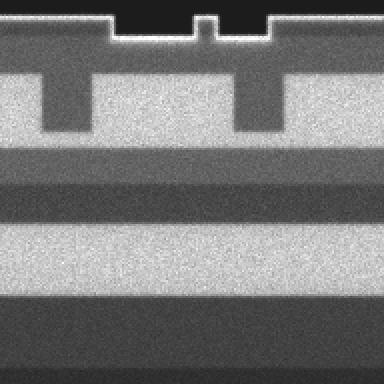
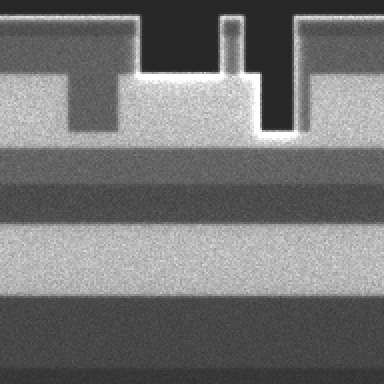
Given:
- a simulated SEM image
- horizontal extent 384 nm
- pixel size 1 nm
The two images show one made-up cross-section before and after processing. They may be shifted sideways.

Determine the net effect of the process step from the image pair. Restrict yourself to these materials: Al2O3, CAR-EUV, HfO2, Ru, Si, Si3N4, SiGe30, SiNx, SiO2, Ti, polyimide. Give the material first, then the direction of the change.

SiO2: removed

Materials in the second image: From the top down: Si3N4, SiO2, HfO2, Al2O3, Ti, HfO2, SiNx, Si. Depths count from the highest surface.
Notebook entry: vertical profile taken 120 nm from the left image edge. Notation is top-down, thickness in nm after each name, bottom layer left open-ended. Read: Si3N4 20, SiO2 38, HfO2 74, Al2O3 36, Ti 40, HfO2 72, SiNx 72, Si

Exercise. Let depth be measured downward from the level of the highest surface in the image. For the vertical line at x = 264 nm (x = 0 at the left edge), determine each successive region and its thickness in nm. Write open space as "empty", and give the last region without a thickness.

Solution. empty 116, HfO2 16, Al2O3 36, Ti 40, HfO2 72, SiNx 72, Si